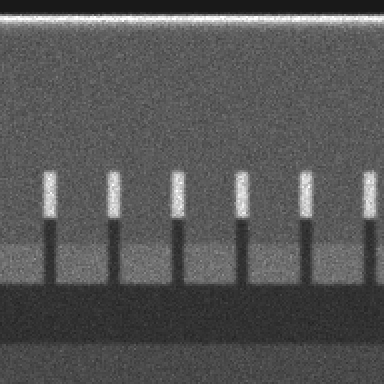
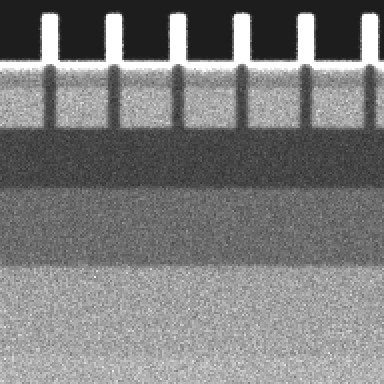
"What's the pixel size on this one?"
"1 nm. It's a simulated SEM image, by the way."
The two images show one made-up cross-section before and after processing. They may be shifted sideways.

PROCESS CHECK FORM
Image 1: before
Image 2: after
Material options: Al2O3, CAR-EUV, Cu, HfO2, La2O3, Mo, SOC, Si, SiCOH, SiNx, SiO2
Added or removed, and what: removed, SOC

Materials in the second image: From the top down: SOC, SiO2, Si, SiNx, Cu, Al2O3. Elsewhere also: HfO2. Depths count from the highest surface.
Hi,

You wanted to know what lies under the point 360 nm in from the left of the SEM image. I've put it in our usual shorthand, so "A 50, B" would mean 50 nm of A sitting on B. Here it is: empty 46, SOC 26, SiO2 40, Si 60, SiNx 78, Cu 90, Al2O3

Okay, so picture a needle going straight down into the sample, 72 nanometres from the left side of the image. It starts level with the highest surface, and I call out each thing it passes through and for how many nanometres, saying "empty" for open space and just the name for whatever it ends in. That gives empty 46, SOC 26, SiO2 40, Si 60, SiNx 78, Cu 90, Al2O3